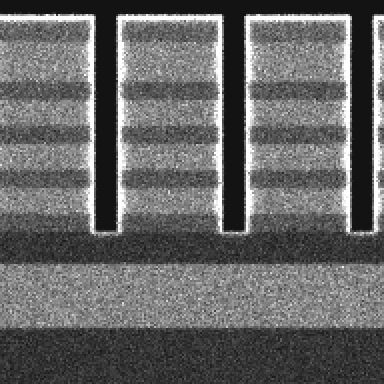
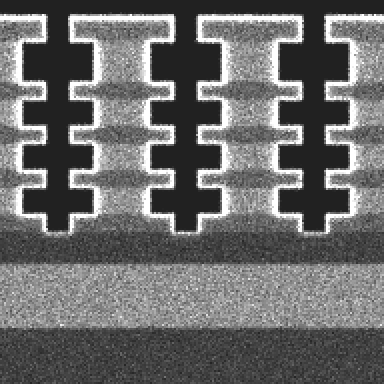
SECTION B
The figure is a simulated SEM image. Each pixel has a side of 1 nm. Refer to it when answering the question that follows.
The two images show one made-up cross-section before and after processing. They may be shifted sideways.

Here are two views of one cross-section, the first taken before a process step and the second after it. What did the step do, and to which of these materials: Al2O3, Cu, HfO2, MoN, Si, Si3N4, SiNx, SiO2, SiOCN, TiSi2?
It removed SiO2.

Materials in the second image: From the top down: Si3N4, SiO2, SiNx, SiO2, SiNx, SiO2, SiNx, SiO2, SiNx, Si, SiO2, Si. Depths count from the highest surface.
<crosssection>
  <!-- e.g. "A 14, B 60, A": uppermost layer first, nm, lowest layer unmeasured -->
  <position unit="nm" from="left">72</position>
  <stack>Si3N4 26, empty 40, SiNx 18, empty 26, SiNx 18, empty 26, SiNx 18, empty 26, SiNx 18, Si 32, SiO2 64, Si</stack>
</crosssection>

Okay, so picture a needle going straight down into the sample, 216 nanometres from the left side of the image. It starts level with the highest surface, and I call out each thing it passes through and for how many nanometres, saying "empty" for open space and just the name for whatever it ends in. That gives Si3N4 26, empty 40, SiNx 18, empty 26, SiNx 18, empty 26, SiNx 18, empty 26, SiNx 18, Si 32, SiO2 64, Si